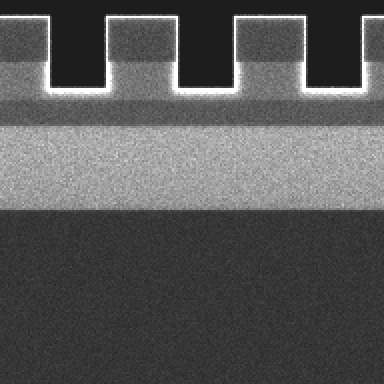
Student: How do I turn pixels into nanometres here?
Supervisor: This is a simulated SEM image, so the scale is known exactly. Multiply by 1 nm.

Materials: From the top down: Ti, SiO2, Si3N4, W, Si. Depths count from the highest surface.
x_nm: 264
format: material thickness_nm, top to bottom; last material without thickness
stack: Ti 46, SiO2 38, Si3N4 26, W 84, Si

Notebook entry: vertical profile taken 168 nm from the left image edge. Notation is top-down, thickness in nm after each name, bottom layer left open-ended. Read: Ti 46, SiO2 38, Si3N4 26, W 84, Si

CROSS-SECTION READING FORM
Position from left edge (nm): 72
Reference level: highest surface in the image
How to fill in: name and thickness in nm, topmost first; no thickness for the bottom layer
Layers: empty 72, SiO2 12, Si3N4 26, W 84, Si